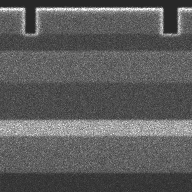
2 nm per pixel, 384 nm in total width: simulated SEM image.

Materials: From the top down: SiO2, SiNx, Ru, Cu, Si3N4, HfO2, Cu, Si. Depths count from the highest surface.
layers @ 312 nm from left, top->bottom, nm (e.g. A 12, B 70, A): SiO2 52, SiNx 34, Ru 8, Cu 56, Si3N4 74, HfO2 32, Cu 74, Si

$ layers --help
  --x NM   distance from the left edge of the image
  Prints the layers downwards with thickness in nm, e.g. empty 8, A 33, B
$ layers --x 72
SiO2 52, SiNx 34, Ru 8, Cu 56, Si3N4 74, HfO2 32, Cu 74, Si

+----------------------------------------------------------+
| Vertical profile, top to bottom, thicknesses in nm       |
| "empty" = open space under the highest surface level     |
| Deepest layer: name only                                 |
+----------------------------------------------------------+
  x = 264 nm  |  SiO2 52, SiNx 34, Ru 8, Cu 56, Si3N4 74, HfO2 32, Cu 74, Si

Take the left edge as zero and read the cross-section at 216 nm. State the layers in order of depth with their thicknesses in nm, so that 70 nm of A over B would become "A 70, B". SiO2 52, SiNx 34, Ru 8, Cu 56, Si3N4 74, HfO2 32, Cu 74, Si